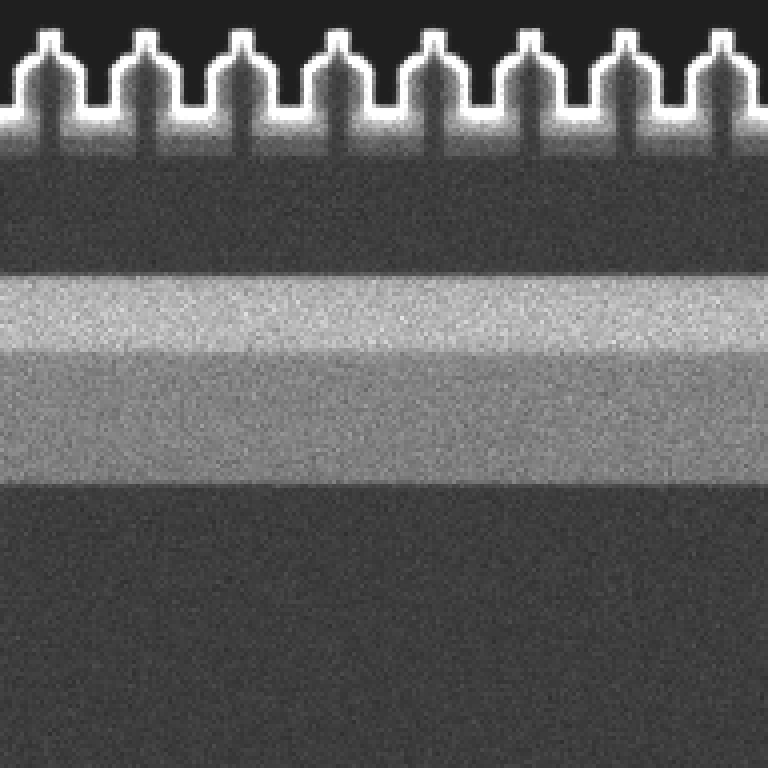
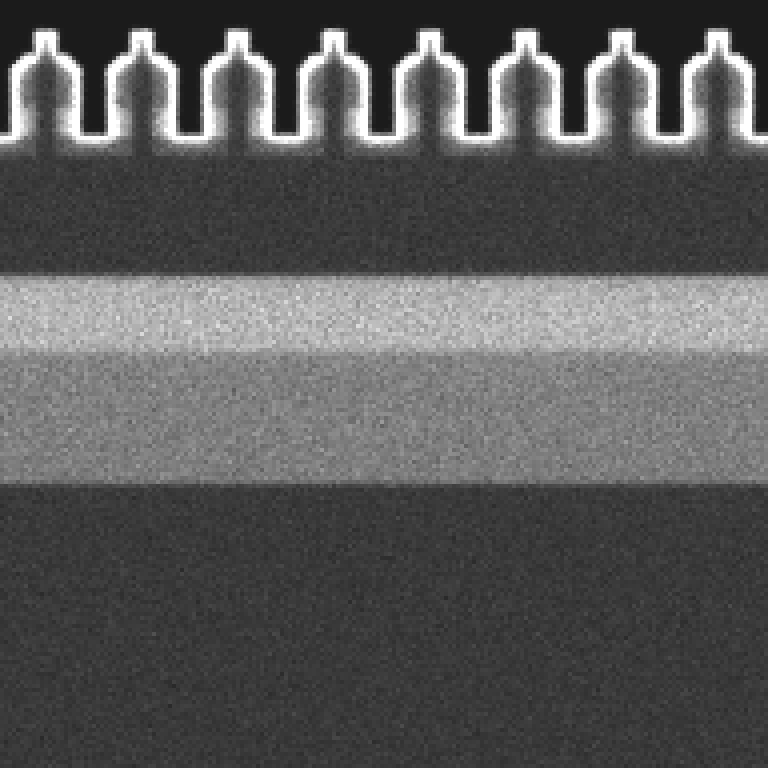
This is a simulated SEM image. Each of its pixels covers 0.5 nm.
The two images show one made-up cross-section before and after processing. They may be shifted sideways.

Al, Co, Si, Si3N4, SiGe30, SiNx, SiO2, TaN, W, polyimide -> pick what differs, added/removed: SiO2 removed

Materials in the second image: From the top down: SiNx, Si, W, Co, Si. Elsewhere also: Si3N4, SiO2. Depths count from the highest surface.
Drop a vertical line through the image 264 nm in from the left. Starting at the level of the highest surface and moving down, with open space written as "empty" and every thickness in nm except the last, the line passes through SiNx 10, Si 112, W 38, Co 66, Si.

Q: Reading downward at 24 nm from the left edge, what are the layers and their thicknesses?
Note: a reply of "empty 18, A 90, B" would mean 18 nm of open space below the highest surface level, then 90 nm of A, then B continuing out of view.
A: SiNx 10, Si 112, W 38, Co 66, Si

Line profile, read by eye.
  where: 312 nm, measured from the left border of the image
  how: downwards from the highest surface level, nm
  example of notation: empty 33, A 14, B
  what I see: SiNx 10, Si 112, W 38, Co 66, Si